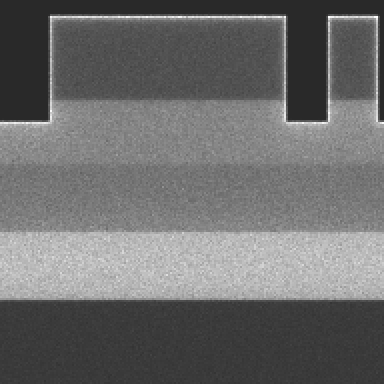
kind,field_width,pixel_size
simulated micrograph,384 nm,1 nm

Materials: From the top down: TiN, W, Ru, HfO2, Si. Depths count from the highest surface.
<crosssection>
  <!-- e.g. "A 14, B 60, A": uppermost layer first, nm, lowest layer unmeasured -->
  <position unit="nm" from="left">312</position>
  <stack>empty 106, W 42, Ru 68, HfO2 68, Si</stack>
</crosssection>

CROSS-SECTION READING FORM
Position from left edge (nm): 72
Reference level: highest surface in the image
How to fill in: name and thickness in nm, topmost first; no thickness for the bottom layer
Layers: TiN 84, W 64, Ru 68, HfO2 68, Si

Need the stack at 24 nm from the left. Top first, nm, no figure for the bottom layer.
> empty 106, W 42, Ru 68, HfO2 68, Si